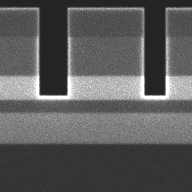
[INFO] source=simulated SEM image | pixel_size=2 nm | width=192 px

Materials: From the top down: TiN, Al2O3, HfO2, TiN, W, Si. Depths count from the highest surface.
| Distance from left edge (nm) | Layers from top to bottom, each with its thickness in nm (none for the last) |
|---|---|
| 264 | TiN 58, Al2O3 78, HfO2 48, TiN 26, W 62, Si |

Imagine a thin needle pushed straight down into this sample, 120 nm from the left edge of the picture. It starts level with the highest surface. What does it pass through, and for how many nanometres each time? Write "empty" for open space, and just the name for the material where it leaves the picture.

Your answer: empty 176, HfO2 8, TiN 26, W 62, Si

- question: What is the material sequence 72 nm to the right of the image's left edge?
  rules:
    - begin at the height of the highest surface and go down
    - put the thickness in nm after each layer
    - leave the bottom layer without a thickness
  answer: TiN 58, Al2O3 78, HfO2 48, TiN 26, W 62, Si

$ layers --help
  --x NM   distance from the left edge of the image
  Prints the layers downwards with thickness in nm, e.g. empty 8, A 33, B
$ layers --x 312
empty 176, HfO2 8, TiN 26, W 62, Si